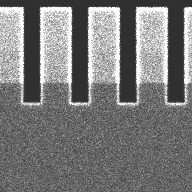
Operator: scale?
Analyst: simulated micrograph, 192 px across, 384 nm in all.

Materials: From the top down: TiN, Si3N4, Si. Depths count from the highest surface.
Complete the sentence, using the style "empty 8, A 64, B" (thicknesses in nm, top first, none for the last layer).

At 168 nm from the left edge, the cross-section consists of empty 190, Si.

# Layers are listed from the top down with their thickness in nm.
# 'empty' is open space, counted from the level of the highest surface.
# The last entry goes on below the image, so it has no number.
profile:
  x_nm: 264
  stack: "empty 190, Si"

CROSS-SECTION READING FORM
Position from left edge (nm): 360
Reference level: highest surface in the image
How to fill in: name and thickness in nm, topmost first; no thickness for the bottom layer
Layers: empty 190, Si